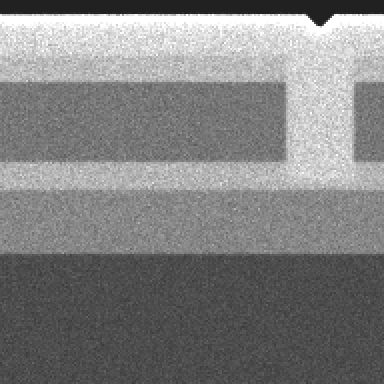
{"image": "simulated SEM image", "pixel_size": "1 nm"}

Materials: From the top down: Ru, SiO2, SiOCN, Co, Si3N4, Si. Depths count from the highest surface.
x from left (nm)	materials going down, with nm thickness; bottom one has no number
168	Ru 40, SiO2 26, SiOCN 80, Co 28, Si3N4 64, Si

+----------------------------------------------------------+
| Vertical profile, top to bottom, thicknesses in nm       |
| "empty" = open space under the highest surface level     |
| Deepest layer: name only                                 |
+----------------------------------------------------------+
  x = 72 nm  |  Ru 40, SiO2 26, SiOCN 80, Co 28, Si3N4 64, Si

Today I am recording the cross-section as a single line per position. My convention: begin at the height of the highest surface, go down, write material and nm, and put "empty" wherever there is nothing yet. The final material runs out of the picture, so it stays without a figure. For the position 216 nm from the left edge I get Ru 40, SiO2 26, SiOCN 80, Co 28, Si3N4 64, Si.